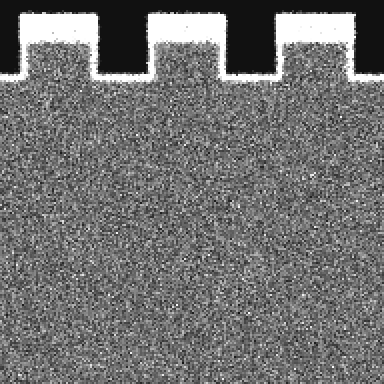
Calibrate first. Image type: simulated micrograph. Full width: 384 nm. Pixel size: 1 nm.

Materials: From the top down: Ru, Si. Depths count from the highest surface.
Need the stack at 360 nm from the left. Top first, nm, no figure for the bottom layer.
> empty 60, Si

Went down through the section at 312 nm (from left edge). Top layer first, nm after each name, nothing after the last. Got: Ru 26, Si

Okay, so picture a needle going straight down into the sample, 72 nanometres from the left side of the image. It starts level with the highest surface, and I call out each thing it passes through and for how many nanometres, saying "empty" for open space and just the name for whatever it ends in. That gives Ru 26, Si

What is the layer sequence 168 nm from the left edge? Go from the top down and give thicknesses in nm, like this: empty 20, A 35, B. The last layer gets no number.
Ru 26, Si